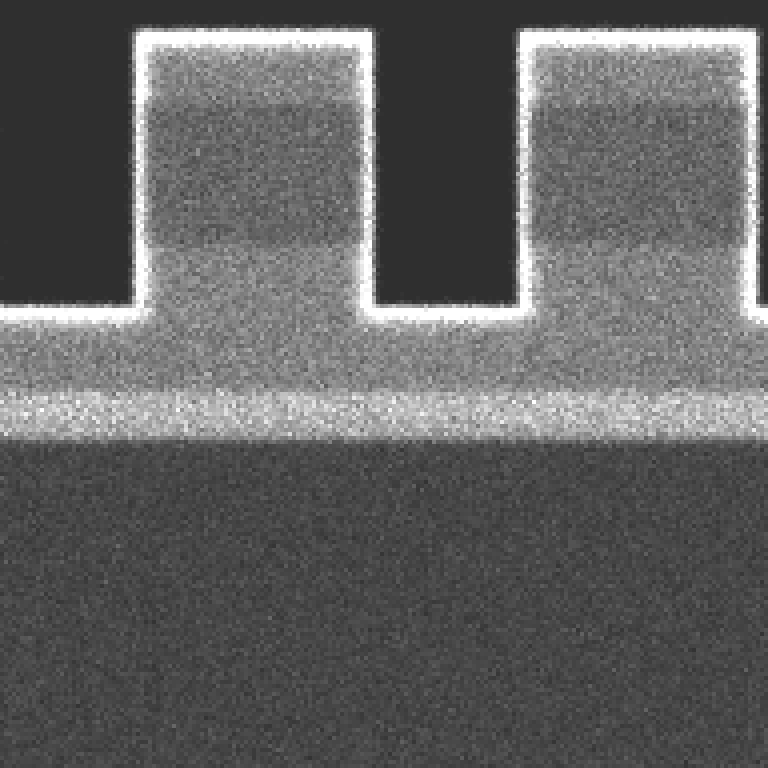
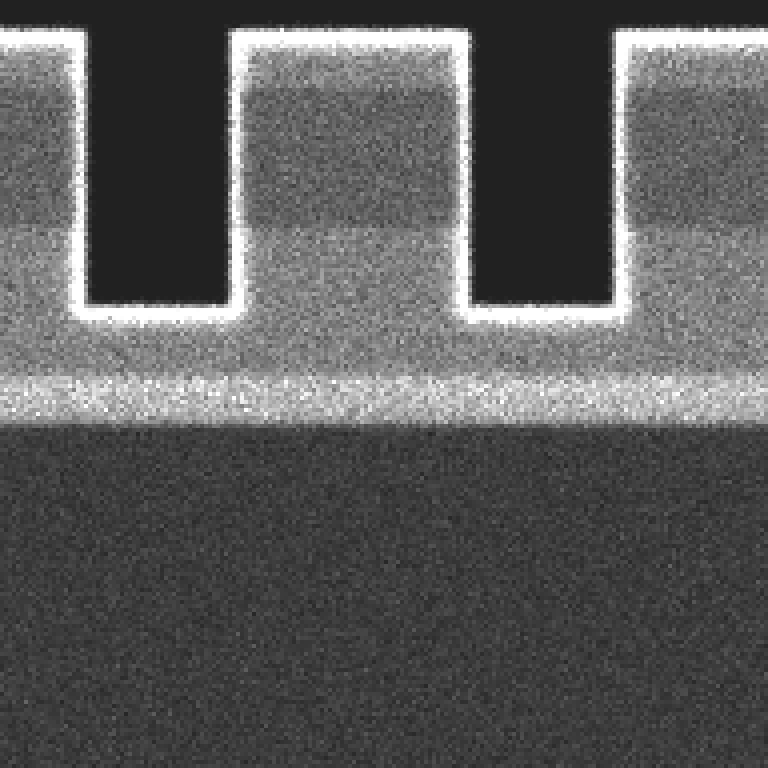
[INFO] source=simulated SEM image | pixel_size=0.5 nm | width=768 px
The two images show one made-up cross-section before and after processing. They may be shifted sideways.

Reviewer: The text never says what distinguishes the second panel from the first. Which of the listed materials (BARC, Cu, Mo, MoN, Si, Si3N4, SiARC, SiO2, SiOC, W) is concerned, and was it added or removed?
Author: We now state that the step removed SiO2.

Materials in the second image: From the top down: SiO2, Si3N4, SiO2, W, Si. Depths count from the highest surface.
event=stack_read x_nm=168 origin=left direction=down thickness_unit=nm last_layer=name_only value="SiO2 28, Si3N4 70, SiO2 74, W 24, Si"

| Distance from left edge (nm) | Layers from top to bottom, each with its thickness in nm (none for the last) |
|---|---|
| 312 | SiO2 28, Si3N4 70, SiO2 74, W 24, Si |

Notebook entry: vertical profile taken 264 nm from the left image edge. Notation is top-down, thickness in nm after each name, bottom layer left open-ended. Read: empty 138, SiO2 34, W 24, Si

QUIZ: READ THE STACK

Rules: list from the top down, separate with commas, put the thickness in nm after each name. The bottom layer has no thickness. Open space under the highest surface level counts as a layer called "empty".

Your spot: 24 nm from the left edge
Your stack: SiO2 28, Si3N4 70, SiO2 74, W 24, Si